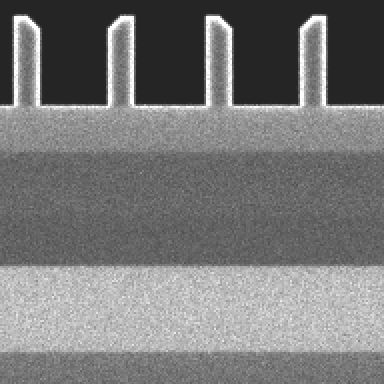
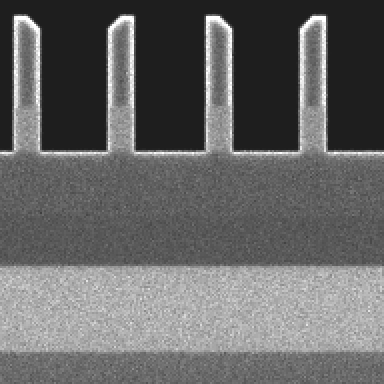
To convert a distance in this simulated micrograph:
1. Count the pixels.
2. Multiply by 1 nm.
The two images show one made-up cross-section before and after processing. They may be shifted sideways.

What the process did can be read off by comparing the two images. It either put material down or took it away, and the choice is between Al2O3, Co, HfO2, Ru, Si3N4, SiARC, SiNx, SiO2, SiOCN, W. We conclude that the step removed W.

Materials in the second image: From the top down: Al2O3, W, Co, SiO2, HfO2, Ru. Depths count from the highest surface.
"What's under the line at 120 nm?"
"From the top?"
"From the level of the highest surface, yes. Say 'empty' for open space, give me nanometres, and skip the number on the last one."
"Al2O3 90, W 46, Co 64, SiO2 50, HfO2 86, Ru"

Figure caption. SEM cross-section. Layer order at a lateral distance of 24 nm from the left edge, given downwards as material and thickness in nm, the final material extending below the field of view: Al2O3 90, W 46, Co 64, SiO2 50, HfO2 86, Ru